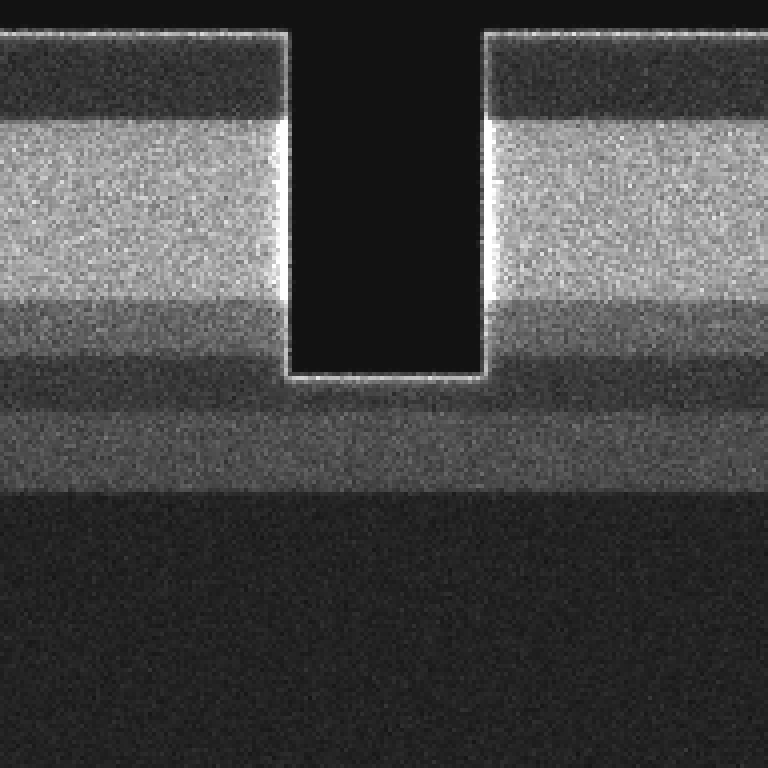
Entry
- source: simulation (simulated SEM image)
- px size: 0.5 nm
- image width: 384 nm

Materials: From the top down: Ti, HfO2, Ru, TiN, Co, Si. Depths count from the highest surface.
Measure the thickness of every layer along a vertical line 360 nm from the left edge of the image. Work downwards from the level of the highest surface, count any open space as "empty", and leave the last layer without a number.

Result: Ti 44, HfO2 90, Ru 28, TiN 28, Co 40, Si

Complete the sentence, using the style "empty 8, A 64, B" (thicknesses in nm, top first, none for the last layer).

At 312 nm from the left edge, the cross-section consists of Ti 44, HfO2 90, Ru 28, TiN 28, Co 40, Si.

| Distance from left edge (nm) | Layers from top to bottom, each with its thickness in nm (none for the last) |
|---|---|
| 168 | empty 172, TiN 18, Co 40, Si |